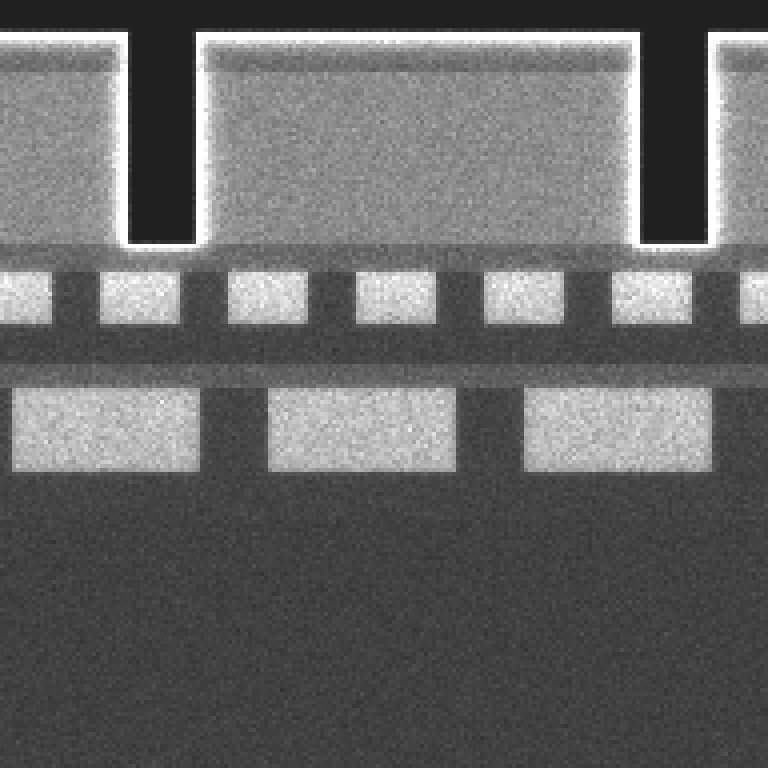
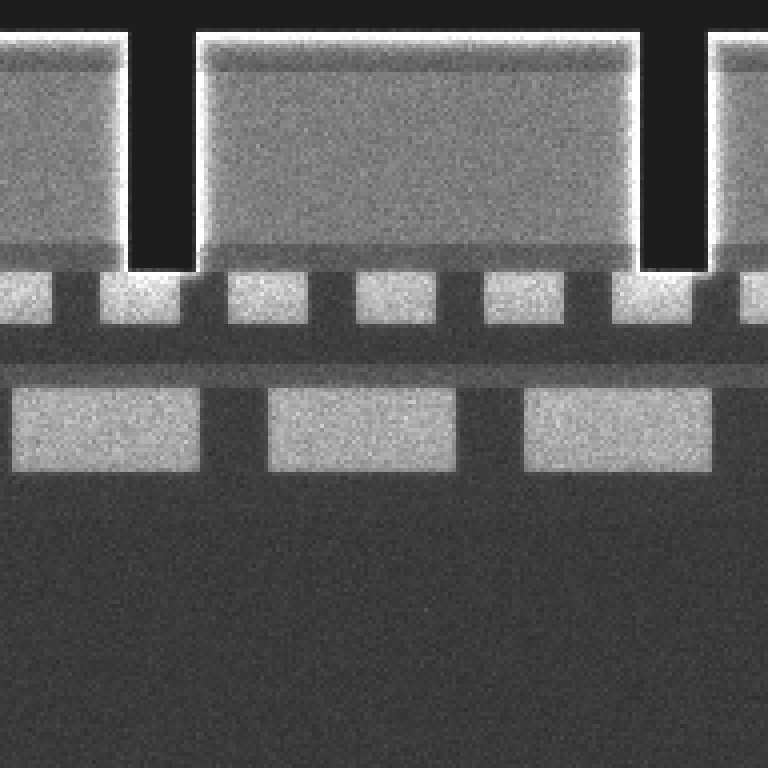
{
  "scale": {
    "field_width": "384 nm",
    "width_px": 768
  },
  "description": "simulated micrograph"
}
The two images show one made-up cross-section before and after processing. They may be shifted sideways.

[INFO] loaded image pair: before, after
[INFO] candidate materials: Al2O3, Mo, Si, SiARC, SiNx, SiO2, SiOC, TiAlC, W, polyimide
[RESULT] removed SiNx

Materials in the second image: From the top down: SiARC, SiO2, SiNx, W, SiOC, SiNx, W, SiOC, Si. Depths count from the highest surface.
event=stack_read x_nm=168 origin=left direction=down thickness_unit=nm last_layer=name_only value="SiARC 20, SiO2 86, SiNx 14, SiOC 46, SiNx 12, W 42, SiOC 24, Si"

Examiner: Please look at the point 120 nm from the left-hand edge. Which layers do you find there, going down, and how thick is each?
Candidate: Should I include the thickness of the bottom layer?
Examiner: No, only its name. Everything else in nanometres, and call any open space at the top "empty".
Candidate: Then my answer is SiARC 20, SiO2 86, SiNx 14, W 26, SiOC 20, SiNx 12, SiOC 66, Si